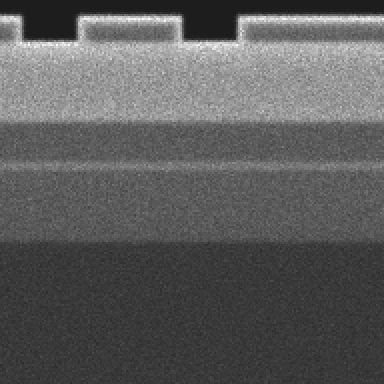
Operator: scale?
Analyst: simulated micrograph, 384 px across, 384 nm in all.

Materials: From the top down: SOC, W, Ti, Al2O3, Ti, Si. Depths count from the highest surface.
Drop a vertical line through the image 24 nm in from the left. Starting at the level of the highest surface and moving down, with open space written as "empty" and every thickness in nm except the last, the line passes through empty 26, W 80, Ti 40, Al2O3 8, Ti 72, Si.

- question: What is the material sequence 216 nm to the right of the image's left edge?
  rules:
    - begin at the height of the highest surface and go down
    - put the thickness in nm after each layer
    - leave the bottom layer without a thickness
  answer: empty 26, W 80, Ti 40, Al2O3 8, Ti 72, Si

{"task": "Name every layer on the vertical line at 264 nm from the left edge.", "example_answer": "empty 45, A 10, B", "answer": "SOC 26, W 80, Ti 40, Al2O3 8, Ti 72, Si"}